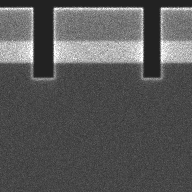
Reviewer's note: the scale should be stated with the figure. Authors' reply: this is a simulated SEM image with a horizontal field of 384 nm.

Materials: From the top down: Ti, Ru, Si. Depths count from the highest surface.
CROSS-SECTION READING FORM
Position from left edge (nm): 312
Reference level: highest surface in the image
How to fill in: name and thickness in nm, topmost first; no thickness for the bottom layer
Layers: empty 140, Si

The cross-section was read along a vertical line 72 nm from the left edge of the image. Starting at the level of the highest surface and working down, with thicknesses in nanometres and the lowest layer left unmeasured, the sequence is empty 140, Si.